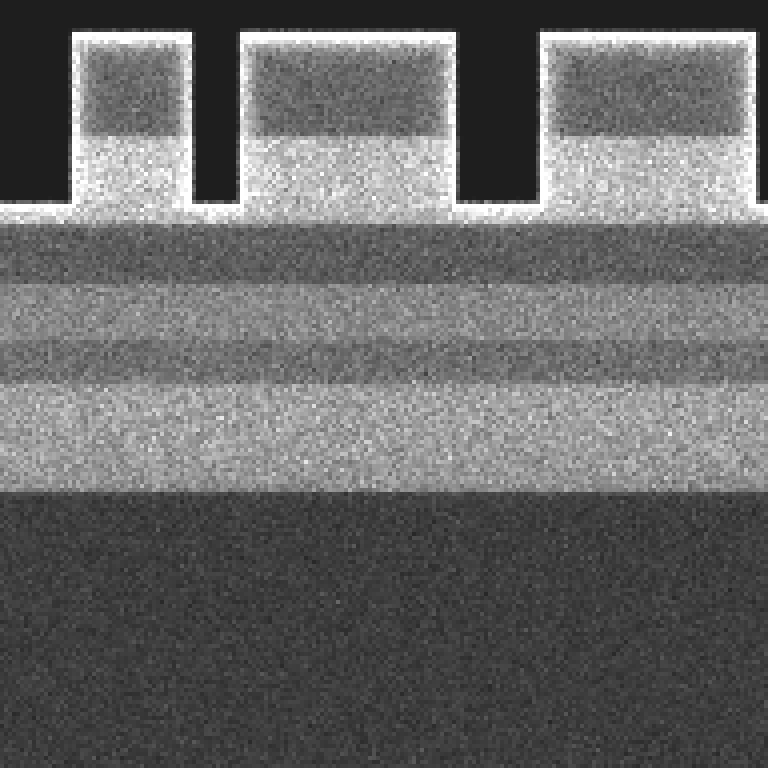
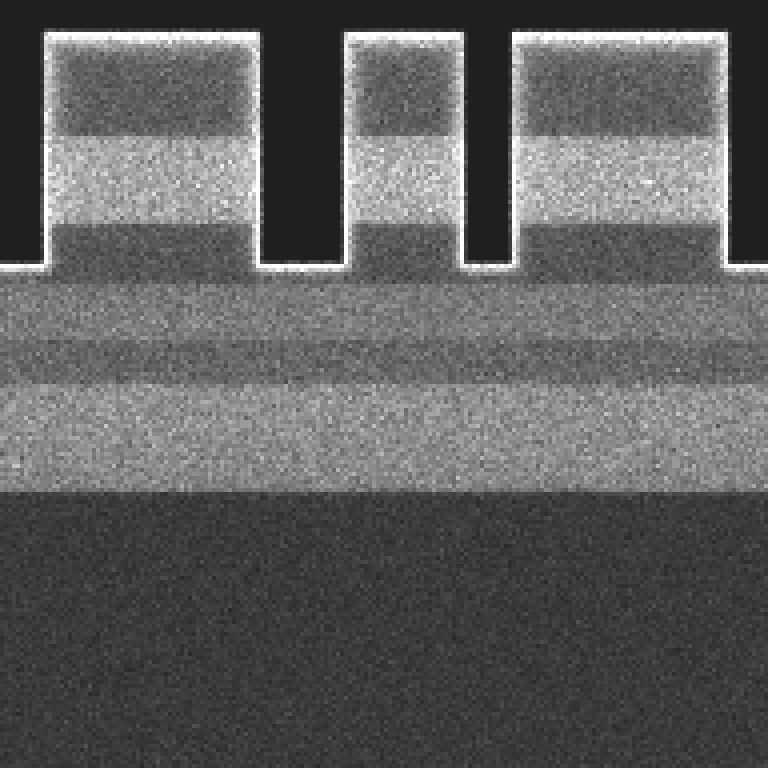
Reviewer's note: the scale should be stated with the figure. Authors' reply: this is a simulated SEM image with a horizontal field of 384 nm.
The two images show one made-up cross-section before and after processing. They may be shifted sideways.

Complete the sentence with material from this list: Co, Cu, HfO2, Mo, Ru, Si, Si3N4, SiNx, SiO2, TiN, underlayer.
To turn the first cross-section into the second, Ru and SiNx must be removed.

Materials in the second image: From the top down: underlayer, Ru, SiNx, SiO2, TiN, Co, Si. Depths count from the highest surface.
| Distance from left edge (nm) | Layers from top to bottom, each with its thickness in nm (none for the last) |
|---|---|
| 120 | underlayer 52, Ru 44, SiNx 30, SiO2 28, TiN 22, Co 54, Si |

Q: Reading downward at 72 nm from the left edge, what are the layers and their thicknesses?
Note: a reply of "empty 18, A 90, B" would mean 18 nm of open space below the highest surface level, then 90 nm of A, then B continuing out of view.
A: underlayer 52, Ru 44, SiNx 30, SiO2 28, TiN 22, Co 54, Si